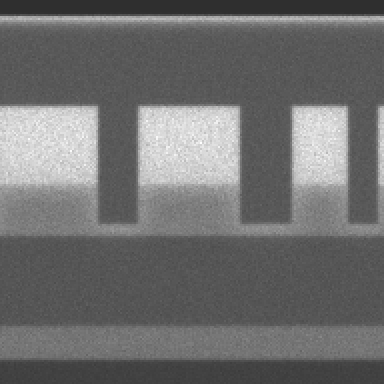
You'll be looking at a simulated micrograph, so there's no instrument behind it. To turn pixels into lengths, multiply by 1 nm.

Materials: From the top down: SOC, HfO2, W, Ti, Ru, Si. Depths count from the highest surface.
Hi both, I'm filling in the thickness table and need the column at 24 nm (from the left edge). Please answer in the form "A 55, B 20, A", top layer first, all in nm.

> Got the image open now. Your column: SOC 90, HfO2 78, W 52, Ti 90, Ru 34, Si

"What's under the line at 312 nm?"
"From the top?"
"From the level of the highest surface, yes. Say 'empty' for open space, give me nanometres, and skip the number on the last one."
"SOC 90, HfO2 78, W 52, Ti 90, Ru 34, Si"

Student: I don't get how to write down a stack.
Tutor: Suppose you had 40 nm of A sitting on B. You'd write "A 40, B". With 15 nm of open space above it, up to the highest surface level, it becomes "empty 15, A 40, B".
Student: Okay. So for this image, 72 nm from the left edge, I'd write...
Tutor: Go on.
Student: SOC 90, HfO2 78, W 52, Ti 90, Ru 34, Si